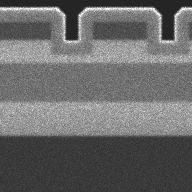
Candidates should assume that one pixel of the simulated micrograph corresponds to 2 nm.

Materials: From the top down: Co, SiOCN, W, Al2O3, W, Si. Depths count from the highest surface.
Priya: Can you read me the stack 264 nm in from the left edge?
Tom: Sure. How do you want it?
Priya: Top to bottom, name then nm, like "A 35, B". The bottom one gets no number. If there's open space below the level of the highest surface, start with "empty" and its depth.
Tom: Co 28, SiOCN 36, W 46, Al2O3 78, W 68, Si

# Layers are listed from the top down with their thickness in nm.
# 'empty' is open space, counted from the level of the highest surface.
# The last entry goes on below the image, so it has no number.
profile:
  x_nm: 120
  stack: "empty 6, Co 88, W 16, Al2O3 78, W 68, Si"